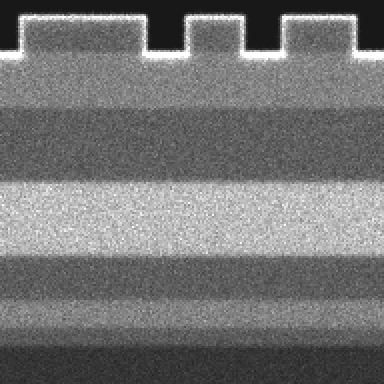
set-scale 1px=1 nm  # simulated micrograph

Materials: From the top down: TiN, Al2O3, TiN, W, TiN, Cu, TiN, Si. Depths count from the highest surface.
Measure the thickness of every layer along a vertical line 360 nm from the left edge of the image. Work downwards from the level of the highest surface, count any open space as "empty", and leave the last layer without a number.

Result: empty 36, Al2O3 56, TiN 74, W 74, TiN 44, Cu 28, TiN 18, Si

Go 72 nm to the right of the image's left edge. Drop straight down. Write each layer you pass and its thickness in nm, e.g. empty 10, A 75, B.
TiN 36, Al2O3 56, TiN 74, W 74, TiN 44, Cu 28, TiN 18, Si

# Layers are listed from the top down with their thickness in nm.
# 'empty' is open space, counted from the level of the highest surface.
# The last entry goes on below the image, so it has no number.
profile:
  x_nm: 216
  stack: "TiN 36, Al2O3 56, TiN 74, W 74, TiN 44, Cu 28, TiN 18, Si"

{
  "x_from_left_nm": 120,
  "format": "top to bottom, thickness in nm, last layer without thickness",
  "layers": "TiN 36, Al2O3 56, TiN 74, W 74, TiN 44, Cu 28, TiN 18, Si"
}